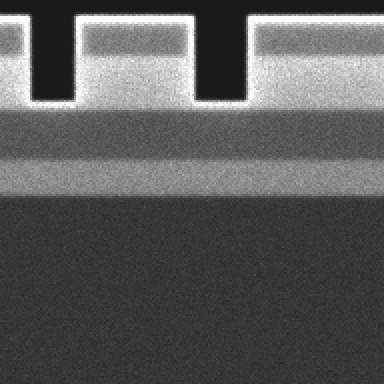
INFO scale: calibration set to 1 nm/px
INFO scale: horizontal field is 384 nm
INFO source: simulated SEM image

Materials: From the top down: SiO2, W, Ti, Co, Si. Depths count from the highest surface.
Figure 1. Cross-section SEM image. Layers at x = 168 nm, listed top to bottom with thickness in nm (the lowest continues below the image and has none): SiO2 40, W 54, Ti 50, Co 36, Si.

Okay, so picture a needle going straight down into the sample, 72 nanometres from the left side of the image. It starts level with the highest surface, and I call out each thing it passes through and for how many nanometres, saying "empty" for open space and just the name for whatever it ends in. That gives empty 86, W 8, Ti 50, Co 36, Si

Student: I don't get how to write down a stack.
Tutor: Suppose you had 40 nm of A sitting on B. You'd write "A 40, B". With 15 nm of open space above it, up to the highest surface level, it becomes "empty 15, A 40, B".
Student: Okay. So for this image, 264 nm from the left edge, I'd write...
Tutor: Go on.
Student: SiO2 40, W 54, Ti 50, Co 36, Si